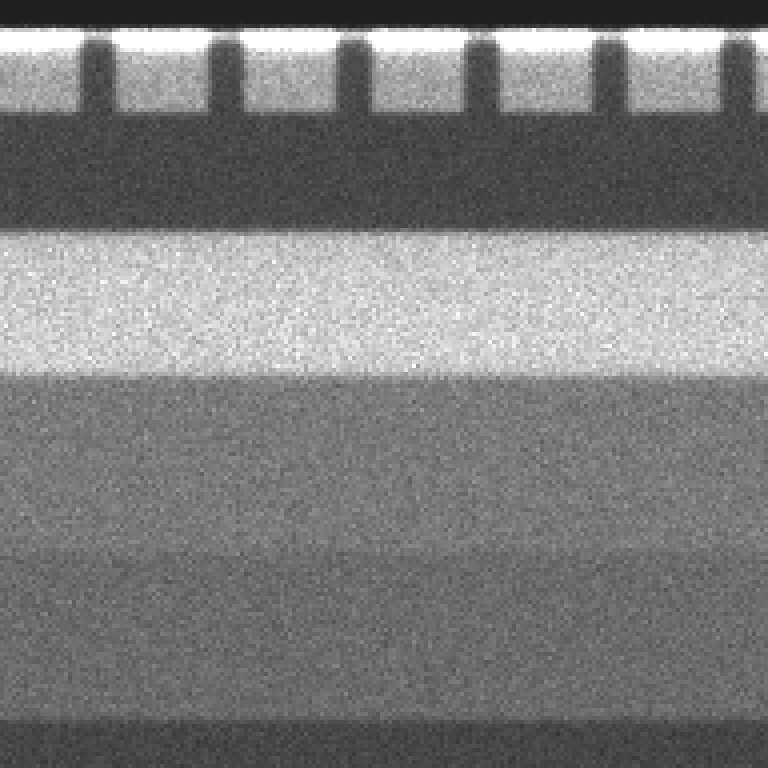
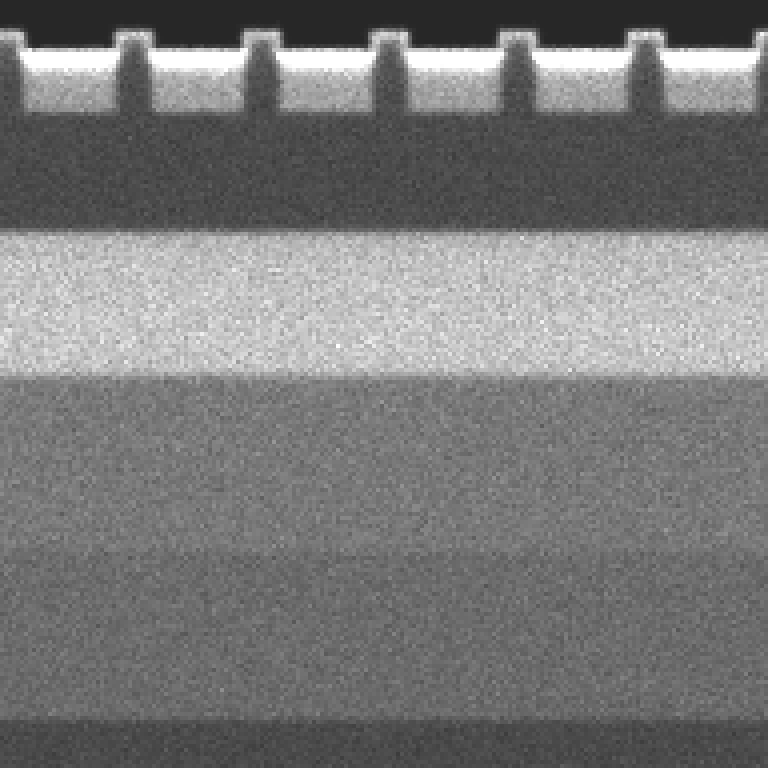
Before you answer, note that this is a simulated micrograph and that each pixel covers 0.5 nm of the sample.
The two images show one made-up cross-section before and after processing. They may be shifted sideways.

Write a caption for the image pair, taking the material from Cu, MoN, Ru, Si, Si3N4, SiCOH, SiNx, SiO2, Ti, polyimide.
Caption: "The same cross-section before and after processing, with SiO2 removed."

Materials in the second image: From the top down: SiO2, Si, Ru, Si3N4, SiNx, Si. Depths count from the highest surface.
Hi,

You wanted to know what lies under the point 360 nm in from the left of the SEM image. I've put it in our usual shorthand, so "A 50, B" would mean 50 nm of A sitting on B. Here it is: empty 10, SiO2 30, Si 60, Ru 72, Si3N4 88, SiNx 84, Si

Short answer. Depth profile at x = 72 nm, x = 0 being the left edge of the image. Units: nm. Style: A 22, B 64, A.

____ Si 100, Ru 72, Si3N4 88, SiNx 84, Si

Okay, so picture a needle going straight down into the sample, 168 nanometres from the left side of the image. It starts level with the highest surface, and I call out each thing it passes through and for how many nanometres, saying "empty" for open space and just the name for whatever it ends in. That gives empty 10, SiO2 30, Si 60, Ru 72, Si3N4 88, SiNx 84, Si